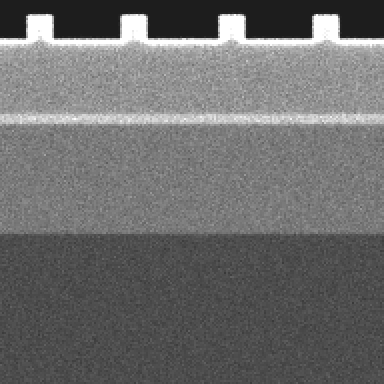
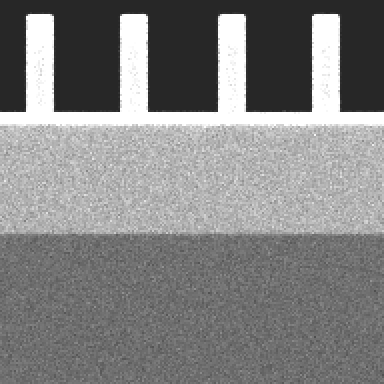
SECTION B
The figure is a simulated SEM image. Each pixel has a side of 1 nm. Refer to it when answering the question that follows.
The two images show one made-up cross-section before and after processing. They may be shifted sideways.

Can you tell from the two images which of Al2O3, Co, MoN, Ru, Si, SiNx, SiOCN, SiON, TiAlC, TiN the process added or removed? Yes, it removed TiN.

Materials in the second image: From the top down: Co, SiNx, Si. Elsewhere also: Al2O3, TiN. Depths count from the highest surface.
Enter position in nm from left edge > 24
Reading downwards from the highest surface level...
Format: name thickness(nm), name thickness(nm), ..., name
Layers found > empty 98, Co 10, SiNx 110, Si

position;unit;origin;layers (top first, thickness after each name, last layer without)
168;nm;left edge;empty 98, Co 10, SiNx 110, Si